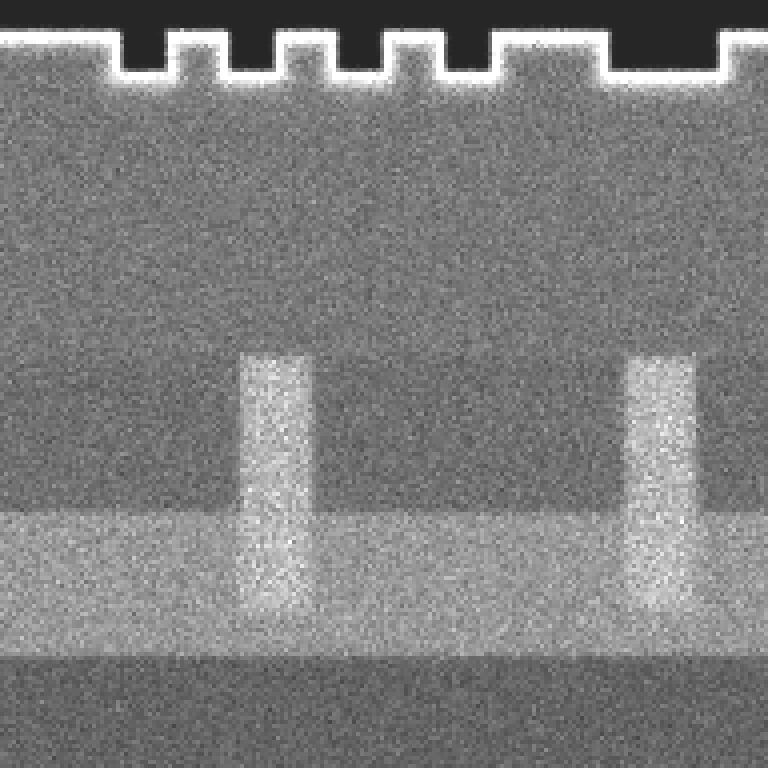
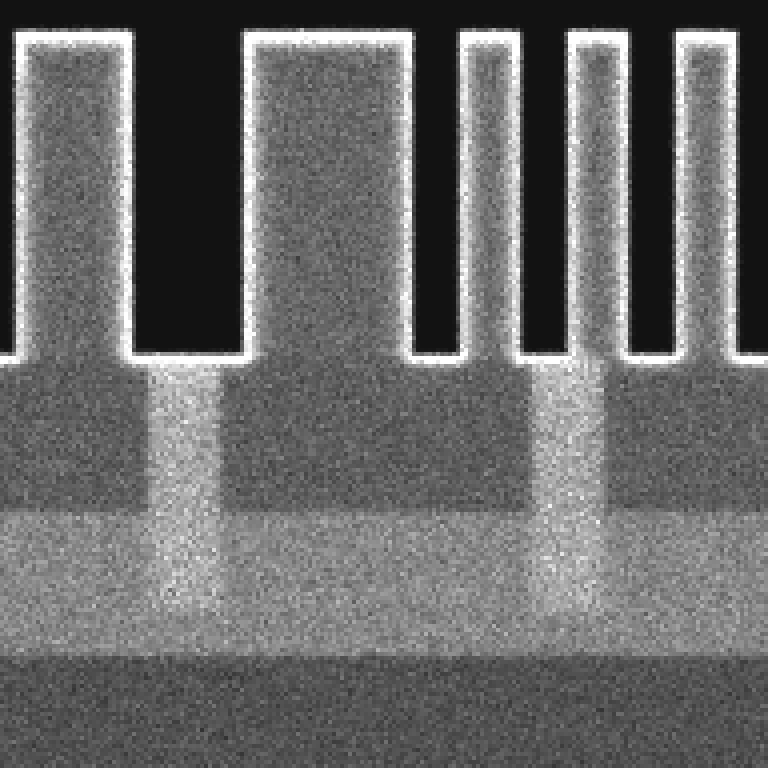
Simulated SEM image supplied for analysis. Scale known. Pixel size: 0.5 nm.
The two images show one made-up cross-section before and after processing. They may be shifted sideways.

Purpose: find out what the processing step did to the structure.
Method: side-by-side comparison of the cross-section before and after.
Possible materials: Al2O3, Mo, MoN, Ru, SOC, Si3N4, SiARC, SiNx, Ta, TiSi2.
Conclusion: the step removed SOC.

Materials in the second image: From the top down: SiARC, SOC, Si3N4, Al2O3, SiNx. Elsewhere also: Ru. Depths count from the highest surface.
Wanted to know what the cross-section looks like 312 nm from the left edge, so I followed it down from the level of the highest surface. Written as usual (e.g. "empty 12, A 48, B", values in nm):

SiARC 20, SOC 142, Si3N4 78, Al2O3 72, SiNx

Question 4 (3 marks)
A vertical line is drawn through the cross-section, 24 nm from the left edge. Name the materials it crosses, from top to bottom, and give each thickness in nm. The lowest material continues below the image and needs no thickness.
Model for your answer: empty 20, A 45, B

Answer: SiARC 20, SOC 142, Si3N4 78, Al2O3 72, SiNx